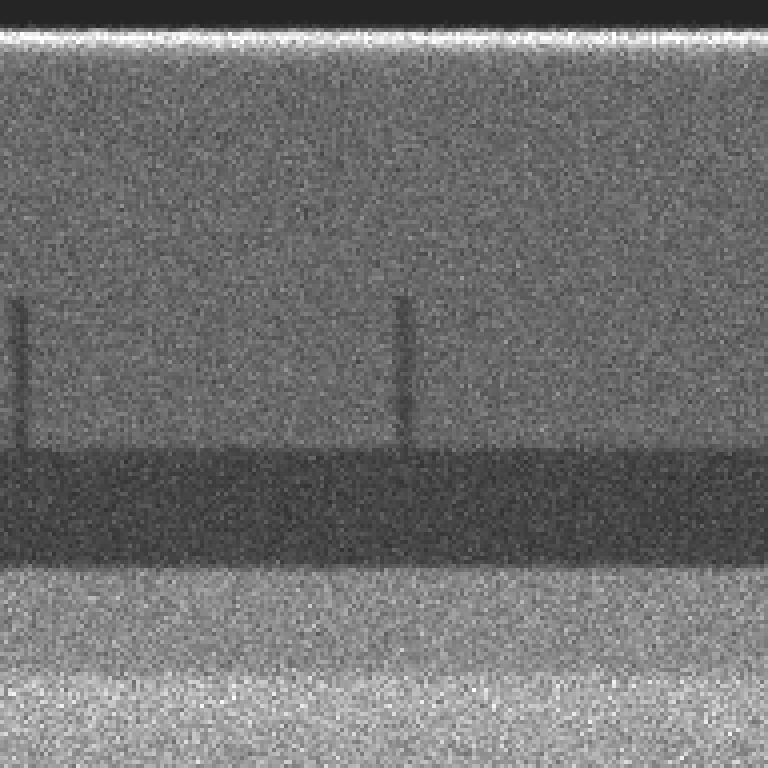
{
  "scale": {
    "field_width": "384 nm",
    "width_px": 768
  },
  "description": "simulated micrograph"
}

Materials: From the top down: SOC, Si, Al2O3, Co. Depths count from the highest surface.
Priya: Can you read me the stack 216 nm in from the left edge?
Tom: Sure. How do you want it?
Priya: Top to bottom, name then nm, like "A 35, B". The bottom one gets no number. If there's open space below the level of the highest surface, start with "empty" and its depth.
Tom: SOC 208, Si 60, Al2O3 54, Co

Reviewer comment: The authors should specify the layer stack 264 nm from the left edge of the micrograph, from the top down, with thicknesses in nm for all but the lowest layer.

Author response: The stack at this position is SOC 208, Si 60, Al2O3 54, Co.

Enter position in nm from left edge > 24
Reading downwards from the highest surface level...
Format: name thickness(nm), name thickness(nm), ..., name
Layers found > SOC 208, Si 60, Al2O3 54, Co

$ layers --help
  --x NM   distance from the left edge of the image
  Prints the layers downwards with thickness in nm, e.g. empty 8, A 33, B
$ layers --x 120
SOC 208, Si 60, Al2O3 54, Co